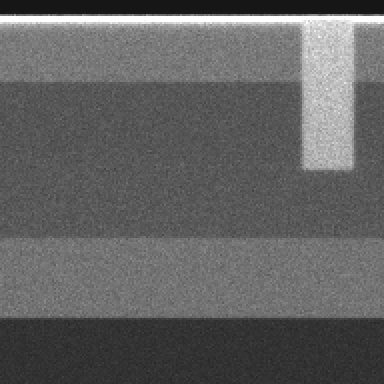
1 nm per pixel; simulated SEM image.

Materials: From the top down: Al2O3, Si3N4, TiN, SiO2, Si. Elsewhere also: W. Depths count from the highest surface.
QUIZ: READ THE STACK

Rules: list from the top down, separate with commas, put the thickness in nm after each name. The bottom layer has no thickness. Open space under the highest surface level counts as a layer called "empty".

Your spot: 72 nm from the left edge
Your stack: Al2O3 66, Si3N4 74, TiN 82, SiO2 80, Si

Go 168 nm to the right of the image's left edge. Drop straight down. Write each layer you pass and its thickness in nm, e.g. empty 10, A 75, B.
Al2O3 66, Si3N4 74, TiN 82, SiO2 80, Si